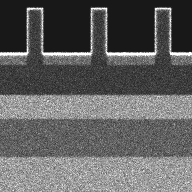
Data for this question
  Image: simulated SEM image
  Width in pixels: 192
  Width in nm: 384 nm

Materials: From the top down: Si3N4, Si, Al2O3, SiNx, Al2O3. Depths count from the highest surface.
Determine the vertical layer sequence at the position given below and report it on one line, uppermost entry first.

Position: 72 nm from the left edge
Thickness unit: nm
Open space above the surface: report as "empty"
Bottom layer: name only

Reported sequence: Si 174, Al2O3 48, SiNx 76, Al2O3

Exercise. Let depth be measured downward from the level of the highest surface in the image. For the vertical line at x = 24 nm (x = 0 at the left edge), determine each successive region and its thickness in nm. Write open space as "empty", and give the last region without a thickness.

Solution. empty 90, Si3N4 24, Si 60, Al2O3 48, SiNx 76, Al2O3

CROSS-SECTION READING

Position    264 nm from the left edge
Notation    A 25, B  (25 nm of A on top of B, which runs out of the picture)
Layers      empty 90, Si3N4 24, Si 60, Al2O3 48, SiNx 76, Al2O3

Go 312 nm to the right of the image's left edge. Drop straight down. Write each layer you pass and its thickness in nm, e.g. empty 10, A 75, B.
Si 174, Al2O3 48, SiNx 76, Al2O3